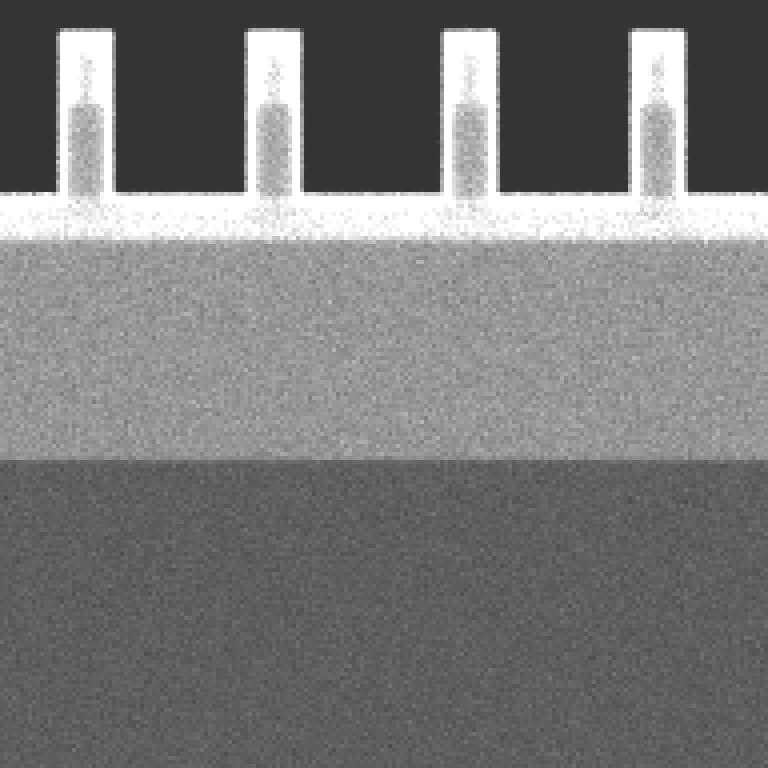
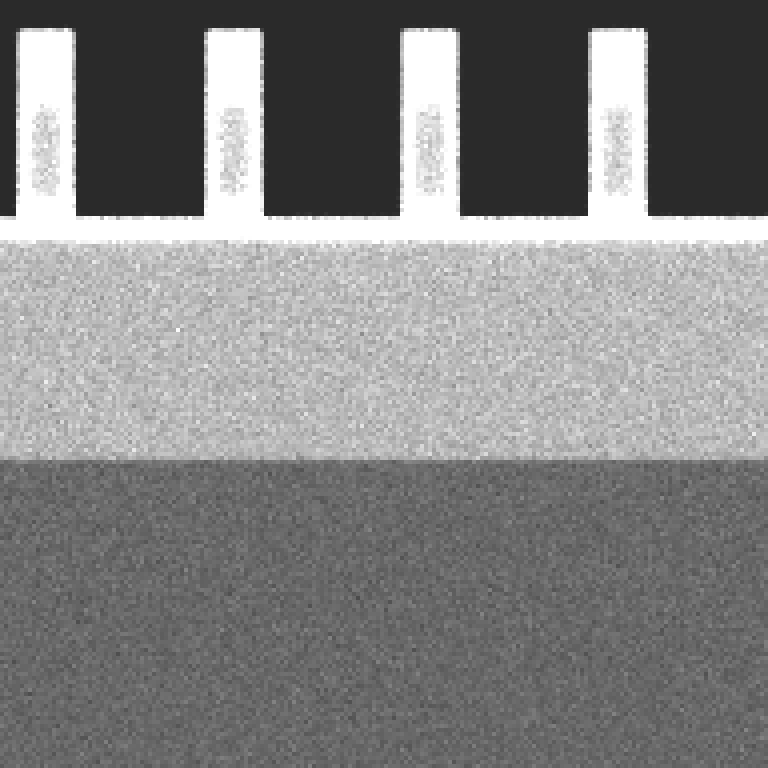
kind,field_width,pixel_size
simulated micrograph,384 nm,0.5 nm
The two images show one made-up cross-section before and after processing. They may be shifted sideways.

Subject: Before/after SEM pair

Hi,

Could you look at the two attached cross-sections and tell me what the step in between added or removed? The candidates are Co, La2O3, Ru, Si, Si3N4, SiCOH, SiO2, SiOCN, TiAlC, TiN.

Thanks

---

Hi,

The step removed Co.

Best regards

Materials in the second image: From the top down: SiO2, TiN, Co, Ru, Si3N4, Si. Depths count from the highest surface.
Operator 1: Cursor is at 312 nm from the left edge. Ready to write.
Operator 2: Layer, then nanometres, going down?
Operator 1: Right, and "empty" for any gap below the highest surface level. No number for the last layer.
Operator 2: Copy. SiO2 36, TiN 46, Co 12, Ru 10, Si3N4 110, Si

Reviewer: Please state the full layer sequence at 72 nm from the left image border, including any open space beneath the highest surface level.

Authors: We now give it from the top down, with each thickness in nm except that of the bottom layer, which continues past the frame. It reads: empty 94, Ru 10, Si3N4 110, Si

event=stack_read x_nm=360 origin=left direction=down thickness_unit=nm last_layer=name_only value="empty 94, Ru 10, Si3N4 110, Si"